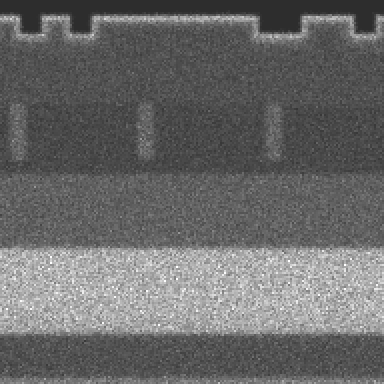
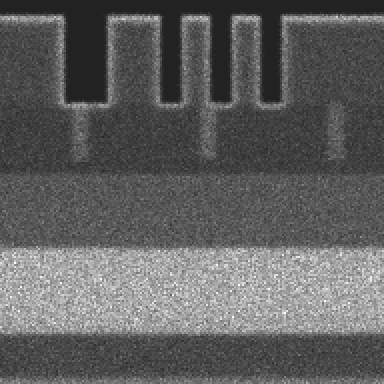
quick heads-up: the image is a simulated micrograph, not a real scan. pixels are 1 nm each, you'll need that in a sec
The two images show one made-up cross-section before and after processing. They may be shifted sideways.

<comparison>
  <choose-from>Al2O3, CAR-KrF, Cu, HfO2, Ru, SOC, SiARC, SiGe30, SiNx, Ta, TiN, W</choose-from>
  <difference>SOC removed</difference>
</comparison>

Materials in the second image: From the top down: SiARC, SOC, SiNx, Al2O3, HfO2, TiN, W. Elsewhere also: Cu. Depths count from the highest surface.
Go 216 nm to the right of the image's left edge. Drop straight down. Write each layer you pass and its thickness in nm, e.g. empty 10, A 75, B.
empty 88, SiNx 70, Al2O3 74, HfO2 86, TiN 44, W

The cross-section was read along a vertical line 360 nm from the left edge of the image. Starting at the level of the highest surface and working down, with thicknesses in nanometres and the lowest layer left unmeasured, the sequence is SiARC 18, SOC 70, SiNx 70, Al2O3 74, HfO2 86, TiN 44, W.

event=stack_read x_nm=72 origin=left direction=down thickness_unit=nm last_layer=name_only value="empty 88, Cu 56, SiNx 14, Al2O3 74, HfO2 86, TiN 44, W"